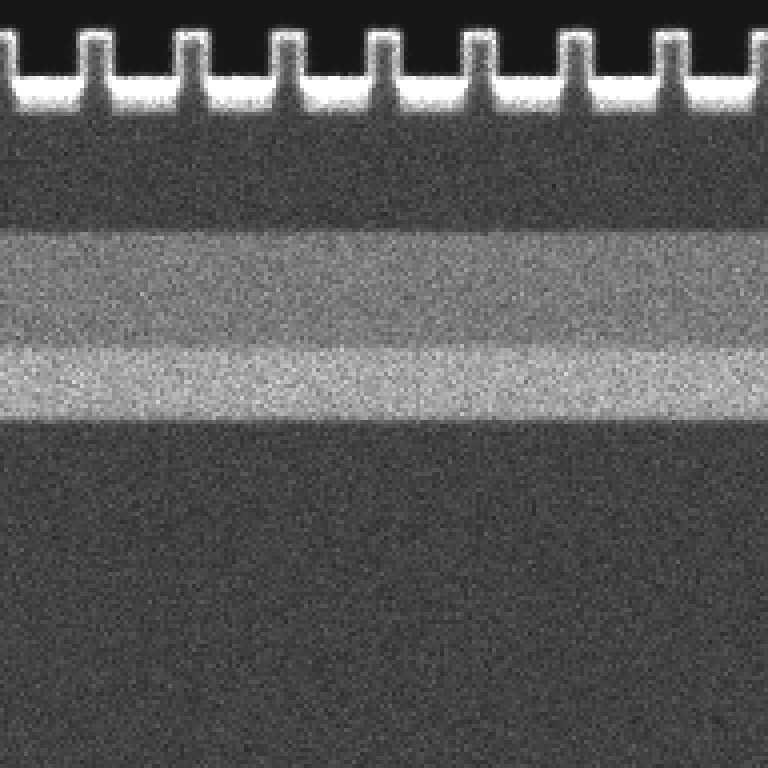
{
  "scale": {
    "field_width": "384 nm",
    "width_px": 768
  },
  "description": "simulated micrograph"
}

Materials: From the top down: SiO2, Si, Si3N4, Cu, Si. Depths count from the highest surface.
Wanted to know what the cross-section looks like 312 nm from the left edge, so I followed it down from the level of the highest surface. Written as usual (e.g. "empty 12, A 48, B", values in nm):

empty 24, SiO2 16, Si 60, Si3N4 58, Cu 36, Si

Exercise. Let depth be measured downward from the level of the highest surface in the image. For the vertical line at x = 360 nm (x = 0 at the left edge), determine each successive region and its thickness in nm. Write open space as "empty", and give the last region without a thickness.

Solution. empty 24, SiO2 16, Si 60, Si3N4 58, Cu 36, Si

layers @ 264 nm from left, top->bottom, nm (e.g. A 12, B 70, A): empty 24, SiO2 16, Si 60, Si3N4 58, Cu 36, Si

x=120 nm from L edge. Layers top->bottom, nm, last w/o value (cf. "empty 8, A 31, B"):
empty 24, SiO2 16, Si 60, Si3N4 58, Cu 36, Si